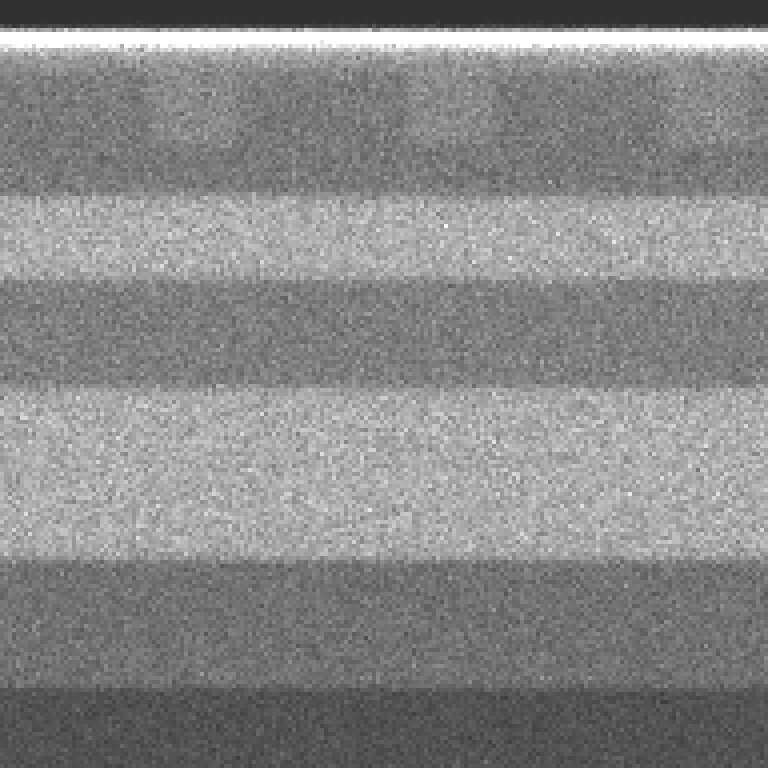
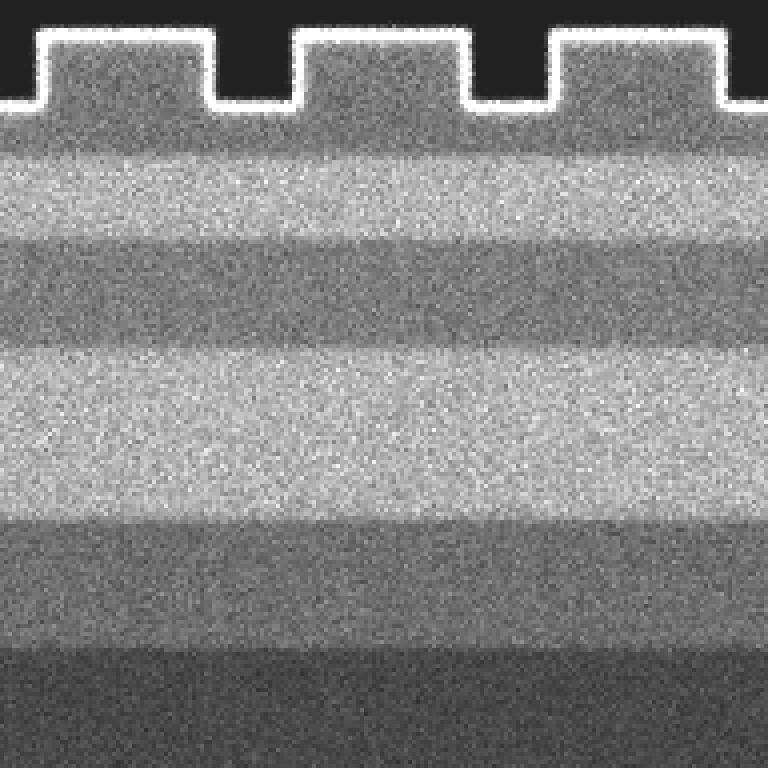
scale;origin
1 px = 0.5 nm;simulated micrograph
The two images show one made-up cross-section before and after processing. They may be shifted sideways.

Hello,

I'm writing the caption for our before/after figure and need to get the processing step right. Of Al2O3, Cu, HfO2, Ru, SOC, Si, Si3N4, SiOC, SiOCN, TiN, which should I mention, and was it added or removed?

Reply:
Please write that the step removed SOC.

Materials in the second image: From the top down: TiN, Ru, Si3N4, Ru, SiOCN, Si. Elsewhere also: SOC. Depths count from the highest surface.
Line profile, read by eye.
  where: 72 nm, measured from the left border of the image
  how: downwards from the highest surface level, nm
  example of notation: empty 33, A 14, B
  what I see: TiN 62, Ru 42, Si3N4 54, Ru 86, SiOCN 64, Si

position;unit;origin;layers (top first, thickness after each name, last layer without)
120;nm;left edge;empty 36, TiN 26, Ru 42, Si3N4 54, Ru 86, SiOCN 64, Si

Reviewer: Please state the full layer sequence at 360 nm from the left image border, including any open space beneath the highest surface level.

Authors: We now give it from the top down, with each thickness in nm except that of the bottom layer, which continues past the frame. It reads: TiN 62, Ru 42, Si3N4 54, Ru 86, SiOCN 64, Si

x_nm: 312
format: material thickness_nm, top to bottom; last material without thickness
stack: TiN 62, Ru 42, Si3N4 54, Ru 86, SiOCN 64, Si